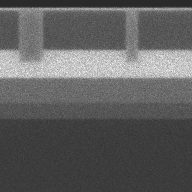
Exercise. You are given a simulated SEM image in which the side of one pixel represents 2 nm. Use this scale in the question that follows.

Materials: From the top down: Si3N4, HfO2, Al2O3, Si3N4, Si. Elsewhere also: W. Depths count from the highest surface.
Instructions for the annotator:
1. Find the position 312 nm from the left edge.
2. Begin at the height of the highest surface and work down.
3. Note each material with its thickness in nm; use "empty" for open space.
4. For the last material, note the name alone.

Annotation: Si3N4 84, HfO2 56, Al2O3 50, Si3N4 32, Si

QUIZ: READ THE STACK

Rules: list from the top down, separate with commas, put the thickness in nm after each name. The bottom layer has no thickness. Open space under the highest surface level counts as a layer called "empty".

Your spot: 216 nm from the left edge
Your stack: Si3N4 84, HfO2 56, Al2O3 50, Si3N4 32, Si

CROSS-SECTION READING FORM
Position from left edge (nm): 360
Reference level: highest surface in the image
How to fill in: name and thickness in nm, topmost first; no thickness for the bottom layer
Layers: Si3N4 84, HfO2 56, Al2O3 50, Si3N4 32, Si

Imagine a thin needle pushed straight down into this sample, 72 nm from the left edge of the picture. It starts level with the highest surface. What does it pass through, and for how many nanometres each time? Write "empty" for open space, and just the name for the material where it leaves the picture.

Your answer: W 108, HfO2 32, Al2O3 50, Si3N4 32, Si